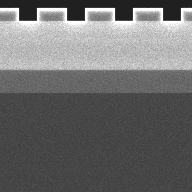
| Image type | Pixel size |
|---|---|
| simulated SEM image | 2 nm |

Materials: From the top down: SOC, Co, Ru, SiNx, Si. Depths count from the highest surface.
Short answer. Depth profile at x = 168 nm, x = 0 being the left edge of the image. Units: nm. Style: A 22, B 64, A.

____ empty 26, Co 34, Ru 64, SiNx 46, Si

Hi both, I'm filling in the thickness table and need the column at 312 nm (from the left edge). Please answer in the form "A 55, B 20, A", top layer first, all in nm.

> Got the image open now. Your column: SOC 26, Co 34, Ru 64, SiNx 46, Si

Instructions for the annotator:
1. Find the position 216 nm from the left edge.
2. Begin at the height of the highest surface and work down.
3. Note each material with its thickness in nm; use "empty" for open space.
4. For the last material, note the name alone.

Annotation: SOC 26, Co 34, Ru 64, SiNx 46, Si